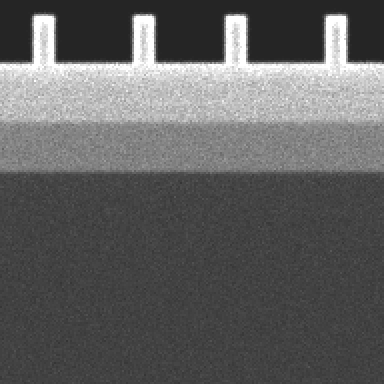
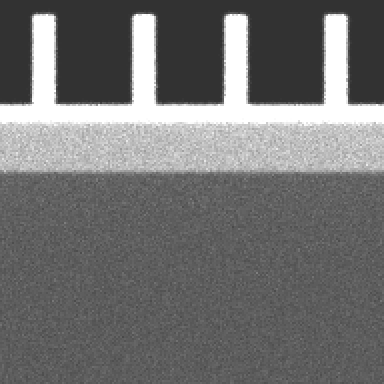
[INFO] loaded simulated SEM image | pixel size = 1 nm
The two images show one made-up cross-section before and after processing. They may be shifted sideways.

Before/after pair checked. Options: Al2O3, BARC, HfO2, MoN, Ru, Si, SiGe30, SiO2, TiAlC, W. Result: removed W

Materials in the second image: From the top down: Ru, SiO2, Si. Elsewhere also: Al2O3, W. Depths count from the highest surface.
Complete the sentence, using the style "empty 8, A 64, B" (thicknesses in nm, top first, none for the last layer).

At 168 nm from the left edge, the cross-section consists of empty 90, Ru 16, SiO2 50, Si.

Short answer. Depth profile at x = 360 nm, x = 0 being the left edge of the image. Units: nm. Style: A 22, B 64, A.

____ empty 90, Ru 16, SiO2 50, Si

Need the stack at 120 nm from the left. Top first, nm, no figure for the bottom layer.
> empty 90, Ru 16, SiO2 50, Si